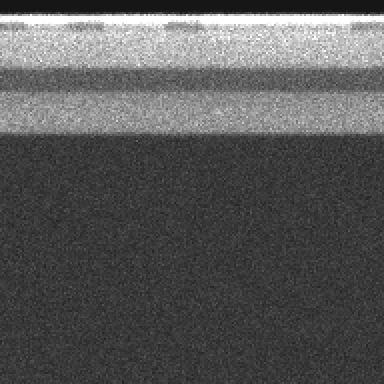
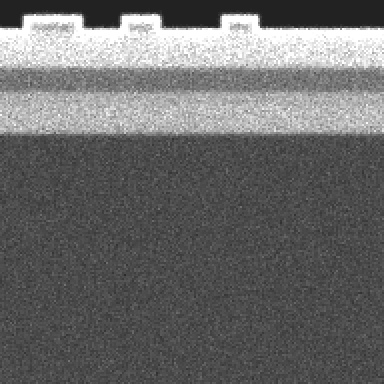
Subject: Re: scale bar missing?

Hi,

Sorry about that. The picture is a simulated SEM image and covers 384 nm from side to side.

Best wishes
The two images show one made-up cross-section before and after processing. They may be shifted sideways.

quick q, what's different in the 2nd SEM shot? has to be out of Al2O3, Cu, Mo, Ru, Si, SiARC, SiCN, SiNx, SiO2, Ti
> SiO2 removed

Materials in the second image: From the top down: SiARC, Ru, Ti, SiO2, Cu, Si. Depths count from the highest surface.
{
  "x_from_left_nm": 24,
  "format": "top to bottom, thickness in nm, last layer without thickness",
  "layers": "SiARC 14, Ru 38, Ti 24, SiO2 14, Cu 28, Si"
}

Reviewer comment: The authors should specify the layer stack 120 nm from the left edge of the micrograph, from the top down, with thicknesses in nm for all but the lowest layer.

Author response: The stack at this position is empty 14, Ru 38, Ti 24, SiO2 14, Cu 28, Si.